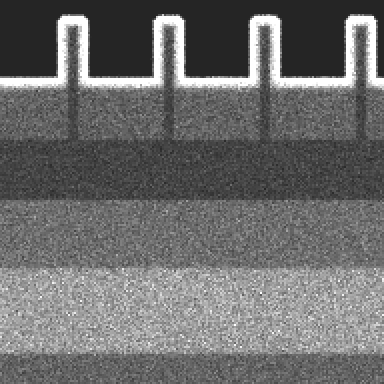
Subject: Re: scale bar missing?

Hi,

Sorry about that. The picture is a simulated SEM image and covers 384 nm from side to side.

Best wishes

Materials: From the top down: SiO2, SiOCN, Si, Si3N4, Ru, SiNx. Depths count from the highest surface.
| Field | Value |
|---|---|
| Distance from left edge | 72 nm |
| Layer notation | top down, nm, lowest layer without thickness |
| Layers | SiO2 10, Si 174, Si3N4 68, Ru 86, SiNx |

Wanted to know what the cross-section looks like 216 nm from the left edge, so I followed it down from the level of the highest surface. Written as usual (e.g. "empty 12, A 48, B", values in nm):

empty 62, SiO2 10, SiOCN 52, Si 60, Si3N4 68, Ru 86, SiNx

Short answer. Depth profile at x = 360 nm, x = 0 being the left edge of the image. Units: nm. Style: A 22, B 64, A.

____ SiO2 10, Si 174, Si3N4 68, Ru 86, SiNx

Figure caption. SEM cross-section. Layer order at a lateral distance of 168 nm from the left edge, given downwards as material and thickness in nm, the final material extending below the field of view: SiO2 10, Si 174, Si3N4 68, Ru 86, SiNx